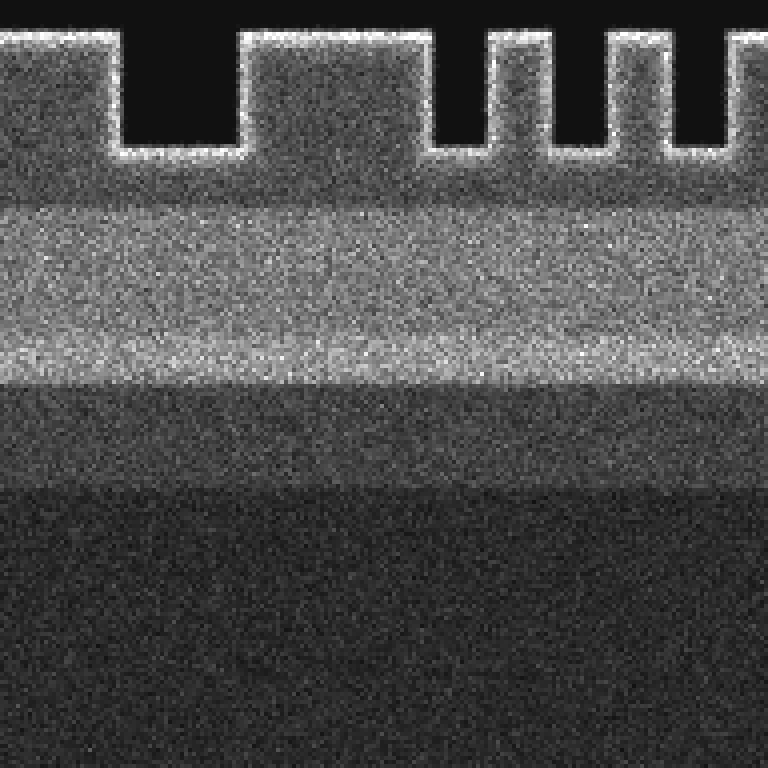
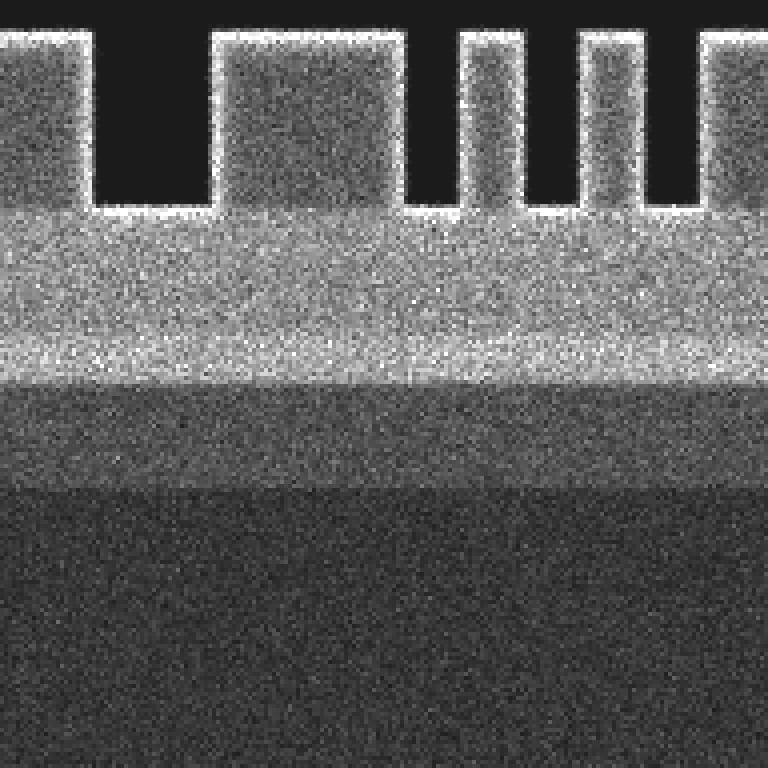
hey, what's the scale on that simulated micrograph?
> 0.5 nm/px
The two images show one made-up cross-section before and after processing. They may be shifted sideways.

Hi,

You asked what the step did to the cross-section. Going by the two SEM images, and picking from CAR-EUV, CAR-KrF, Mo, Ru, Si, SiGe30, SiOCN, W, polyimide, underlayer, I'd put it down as underlayer, removed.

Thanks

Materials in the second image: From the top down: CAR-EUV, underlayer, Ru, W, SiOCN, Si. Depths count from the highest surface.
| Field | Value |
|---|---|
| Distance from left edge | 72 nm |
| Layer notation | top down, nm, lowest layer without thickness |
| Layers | empty 88, Ru 64, W 24, SiOCN 52, Si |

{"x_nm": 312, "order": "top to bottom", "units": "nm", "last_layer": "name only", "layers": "CAR-EUV 58, underlayer 30, Ru 64, W 24, SiOCN 52, Si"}